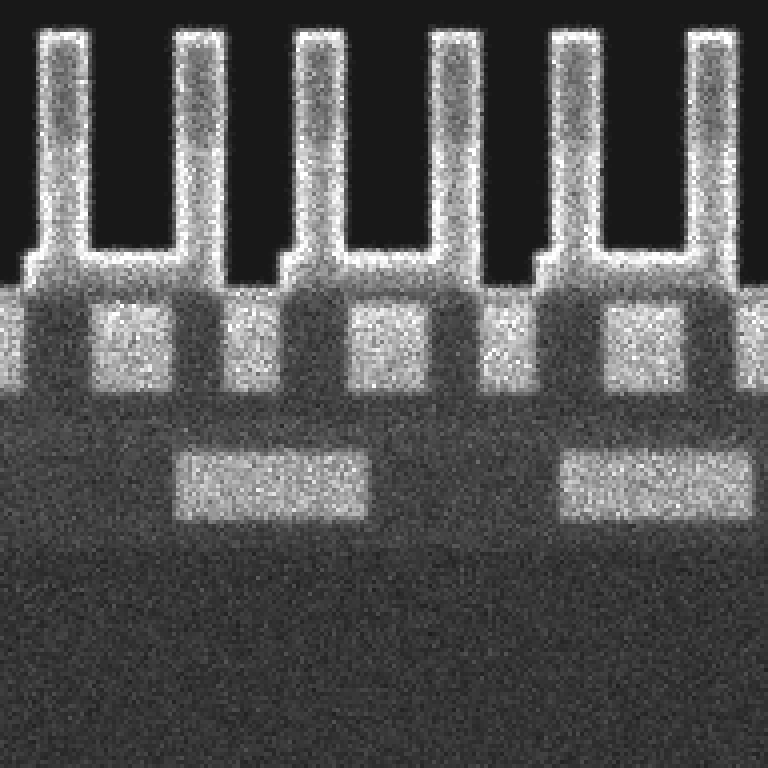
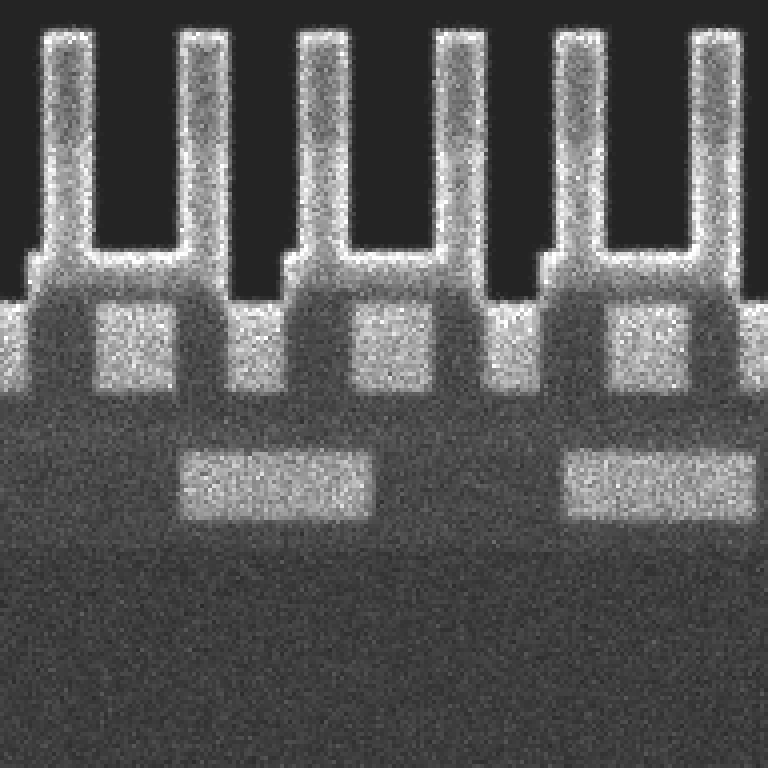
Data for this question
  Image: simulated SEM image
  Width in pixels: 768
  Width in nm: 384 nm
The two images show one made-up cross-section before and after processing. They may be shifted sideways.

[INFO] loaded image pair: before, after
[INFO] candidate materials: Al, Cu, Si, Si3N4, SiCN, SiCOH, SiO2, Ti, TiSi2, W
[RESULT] removed SiCN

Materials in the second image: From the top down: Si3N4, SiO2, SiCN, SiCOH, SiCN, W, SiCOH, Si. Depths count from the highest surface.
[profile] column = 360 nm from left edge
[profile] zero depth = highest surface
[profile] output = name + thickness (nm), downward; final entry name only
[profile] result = Si3N4 56, SiO2 72, SiCN 8, SiCOH 58, SiCN 16, W 34, SiCOH 14, Si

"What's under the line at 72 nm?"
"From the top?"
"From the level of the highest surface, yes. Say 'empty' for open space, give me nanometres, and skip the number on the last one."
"empty 110, SiO2 18, SiCN 8, W 44, SiCOH 14, SiCN 16, SiCOH 48, Si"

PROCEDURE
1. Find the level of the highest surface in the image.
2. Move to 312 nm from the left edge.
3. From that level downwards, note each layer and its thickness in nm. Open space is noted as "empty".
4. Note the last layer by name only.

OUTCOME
empty 110, SiO2 18, SiCN 8, W 44, SiCOH 14, SiCN 16, W 34, SiCOH 14, Si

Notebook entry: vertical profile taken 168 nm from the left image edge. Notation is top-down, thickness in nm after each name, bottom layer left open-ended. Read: Si3N4 56, SiO2 72, SiCN 8, SiCOH 58, SiCN 16, W 34, SiCOH 14, Si